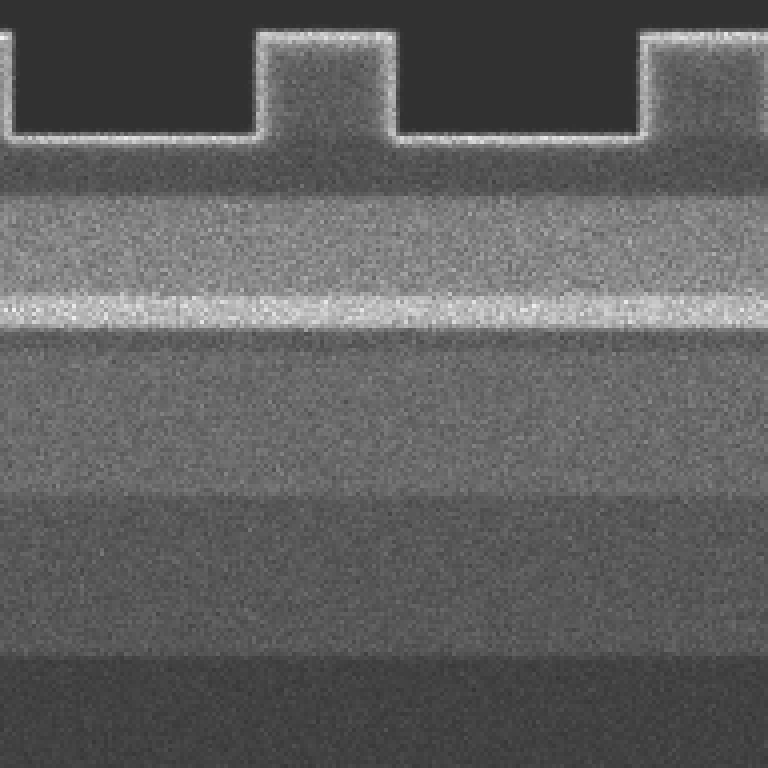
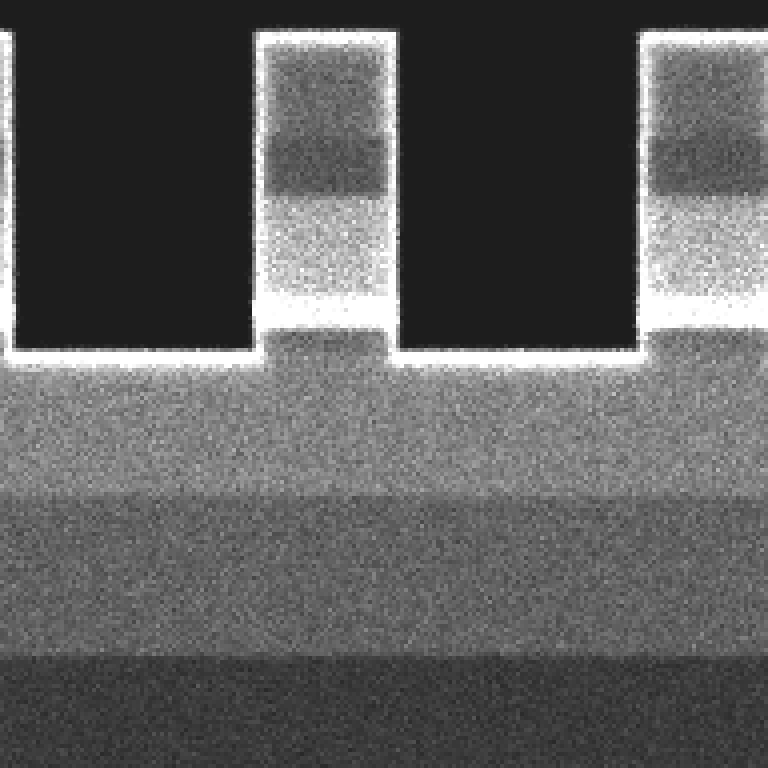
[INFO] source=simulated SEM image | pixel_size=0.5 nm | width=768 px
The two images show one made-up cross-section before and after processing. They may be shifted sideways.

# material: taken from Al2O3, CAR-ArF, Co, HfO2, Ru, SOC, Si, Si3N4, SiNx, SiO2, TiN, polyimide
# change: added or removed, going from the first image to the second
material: HfO2 and Ru and SiNx and TiN
change: removed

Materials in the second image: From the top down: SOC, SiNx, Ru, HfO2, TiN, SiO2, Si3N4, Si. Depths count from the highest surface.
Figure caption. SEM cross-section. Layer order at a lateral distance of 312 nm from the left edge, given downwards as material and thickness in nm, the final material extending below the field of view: empty 160, SiO2 72, Si3N4 80, Si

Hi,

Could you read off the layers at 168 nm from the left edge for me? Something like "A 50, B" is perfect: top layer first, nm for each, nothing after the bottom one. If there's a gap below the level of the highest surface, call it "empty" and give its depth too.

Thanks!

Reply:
SOC 52, SiNx 30, Ru 50, HfO2 16, TiN 12, SiO2 72, Si3N4 80, Si